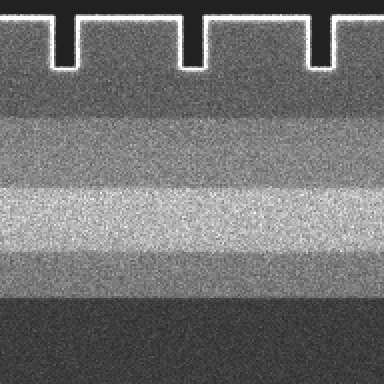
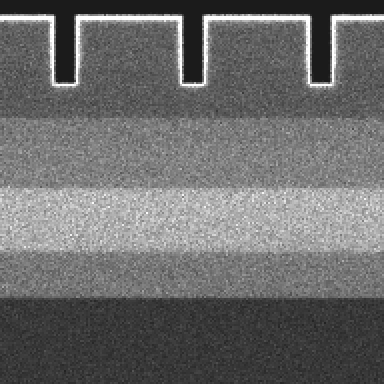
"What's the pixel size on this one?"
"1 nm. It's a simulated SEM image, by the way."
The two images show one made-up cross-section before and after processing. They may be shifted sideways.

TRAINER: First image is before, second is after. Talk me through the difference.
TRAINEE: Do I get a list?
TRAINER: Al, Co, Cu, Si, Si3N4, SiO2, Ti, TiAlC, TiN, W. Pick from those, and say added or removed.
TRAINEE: removed: TiN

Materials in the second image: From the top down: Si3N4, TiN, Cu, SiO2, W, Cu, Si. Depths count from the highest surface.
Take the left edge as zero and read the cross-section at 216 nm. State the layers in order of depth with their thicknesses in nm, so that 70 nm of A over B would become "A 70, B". Si3N4 52, TiN 50, Cu 26, SiO2 44, W 64, Cu 46, Si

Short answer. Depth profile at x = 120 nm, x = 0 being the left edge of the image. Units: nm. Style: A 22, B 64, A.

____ Si3N4 52, TiN 50, Cu 26, SiO2 44, W 64, Cu 46, Si